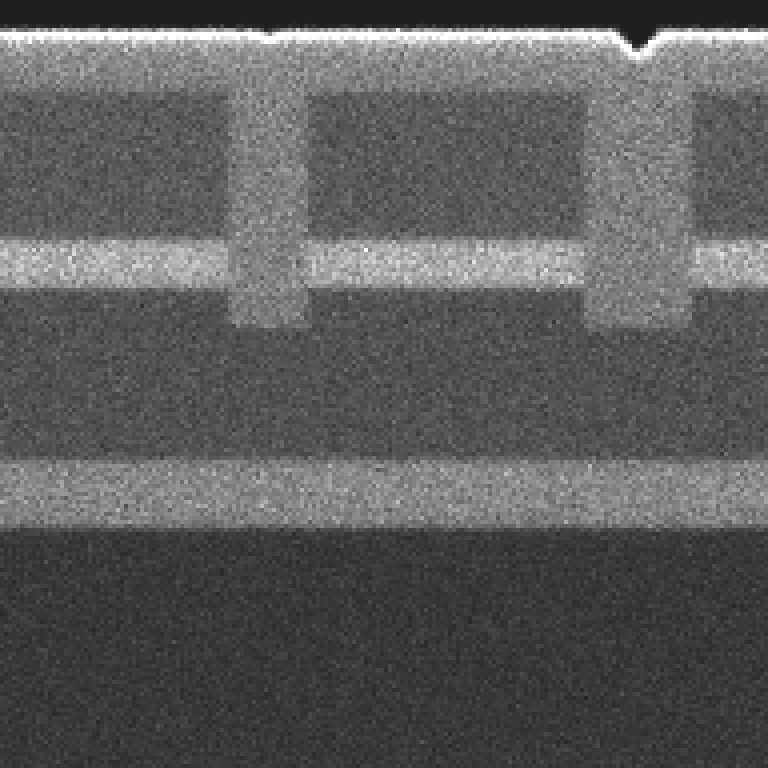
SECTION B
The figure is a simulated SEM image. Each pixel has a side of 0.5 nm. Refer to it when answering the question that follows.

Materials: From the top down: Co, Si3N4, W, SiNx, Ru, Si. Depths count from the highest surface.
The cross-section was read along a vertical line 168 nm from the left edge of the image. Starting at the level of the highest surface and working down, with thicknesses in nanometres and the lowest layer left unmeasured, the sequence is Co 30, Si3N4 74, W 24, SiNx 86, Ru 34, Si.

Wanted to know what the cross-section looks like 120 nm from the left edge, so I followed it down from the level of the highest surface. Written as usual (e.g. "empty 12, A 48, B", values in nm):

Co 148, SiNx 66, Ru 34, Si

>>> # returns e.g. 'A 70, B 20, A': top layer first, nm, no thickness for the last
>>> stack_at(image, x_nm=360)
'Co 30, Si3N4 74, W 24, SiNx 86, Ru 34, Si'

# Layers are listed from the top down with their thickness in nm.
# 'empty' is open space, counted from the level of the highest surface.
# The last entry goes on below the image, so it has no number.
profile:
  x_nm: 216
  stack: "Co 30, Si3N4 74, W 24, SiNx 86, Ru 34, Si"